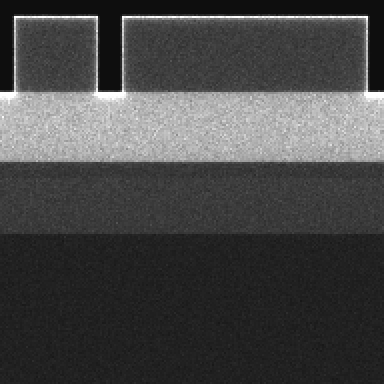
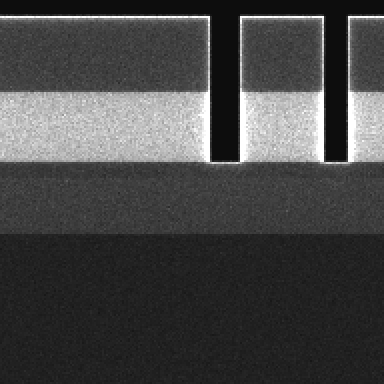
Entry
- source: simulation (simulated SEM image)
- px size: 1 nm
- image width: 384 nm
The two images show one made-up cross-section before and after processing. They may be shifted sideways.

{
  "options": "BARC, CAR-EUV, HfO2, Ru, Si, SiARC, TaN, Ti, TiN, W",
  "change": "removed",
  "material": "HfO2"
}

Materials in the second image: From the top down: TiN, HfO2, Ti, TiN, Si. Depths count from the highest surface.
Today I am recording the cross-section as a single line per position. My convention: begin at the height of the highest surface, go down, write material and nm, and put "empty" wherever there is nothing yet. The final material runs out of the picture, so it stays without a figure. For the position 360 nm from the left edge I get TiN 76, HfO2 70, Ti 16, TiN 56, Si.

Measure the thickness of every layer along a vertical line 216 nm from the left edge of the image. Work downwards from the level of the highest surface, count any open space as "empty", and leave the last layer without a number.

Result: empty 146, Ti 16, TiN 56, Si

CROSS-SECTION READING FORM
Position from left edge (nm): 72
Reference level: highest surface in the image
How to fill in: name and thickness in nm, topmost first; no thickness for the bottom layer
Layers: TiN 76, HfO2 70, Ti 16, TiN 56, Si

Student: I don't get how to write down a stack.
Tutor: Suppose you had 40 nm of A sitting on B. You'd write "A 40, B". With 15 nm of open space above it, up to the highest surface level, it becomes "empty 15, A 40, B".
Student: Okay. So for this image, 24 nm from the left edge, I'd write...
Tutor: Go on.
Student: TiN 76, HfO2 70, Ti 16, TiN 56, Si